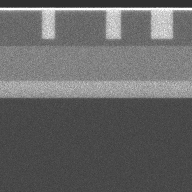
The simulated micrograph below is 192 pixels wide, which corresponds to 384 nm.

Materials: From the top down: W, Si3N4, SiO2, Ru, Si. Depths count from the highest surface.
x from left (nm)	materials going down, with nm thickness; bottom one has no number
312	W 62, Si3N4 14, SiO2 70, Ru 34, Si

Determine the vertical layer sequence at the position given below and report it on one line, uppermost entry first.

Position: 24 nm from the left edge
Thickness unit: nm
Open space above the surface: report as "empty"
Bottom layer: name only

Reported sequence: Si3N4 76, SiO2 70, Ru 34, Si